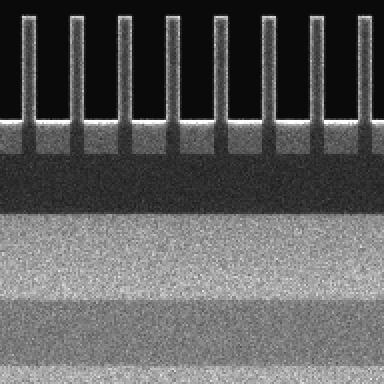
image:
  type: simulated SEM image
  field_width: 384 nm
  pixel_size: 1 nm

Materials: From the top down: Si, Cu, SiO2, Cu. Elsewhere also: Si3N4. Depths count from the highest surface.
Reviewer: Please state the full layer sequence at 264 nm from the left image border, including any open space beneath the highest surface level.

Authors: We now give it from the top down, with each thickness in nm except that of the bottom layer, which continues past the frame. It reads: Si 198, Cu 86, SiO2 66, Cu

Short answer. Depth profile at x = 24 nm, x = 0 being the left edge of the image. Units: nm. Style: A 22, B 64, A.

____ Si 198, Cu 86, SiO2 66, Cu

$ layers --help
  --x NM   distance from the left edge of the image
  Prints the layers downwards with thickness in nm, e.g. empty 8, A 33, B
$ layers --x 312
Si 198, Cu 86, SiO2 66, Cu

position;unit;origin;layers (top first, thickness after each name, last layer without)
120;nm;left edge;Si 198, Cu 86, SiO2 66, Cu